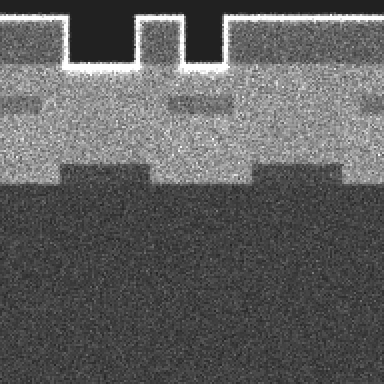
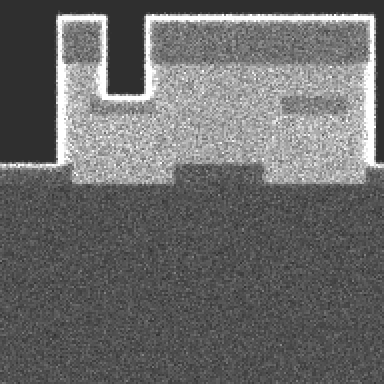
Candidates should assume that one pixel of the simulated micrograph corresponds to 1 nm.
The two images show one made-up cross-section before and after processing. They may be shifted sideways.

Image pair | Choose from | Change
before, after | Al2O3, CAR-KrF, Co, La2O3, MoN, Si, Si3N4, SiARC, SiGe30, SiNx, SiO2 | SiO2 (removed)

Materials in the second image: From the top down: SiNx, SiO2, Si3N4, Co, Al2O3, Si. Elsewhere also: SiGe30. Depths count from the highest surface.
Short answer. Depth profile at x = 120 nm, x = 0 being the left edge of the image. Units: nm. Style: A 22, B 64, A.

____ empty 80, Si3N4 18, Co 58, Al2O3 12, Si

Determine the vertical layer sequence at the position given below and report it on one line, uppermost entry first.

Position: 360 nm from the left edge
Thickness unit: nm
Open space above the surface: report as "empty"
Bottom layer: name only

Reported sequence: SiNx 48, SiO2 36, Al2O3 84, Si